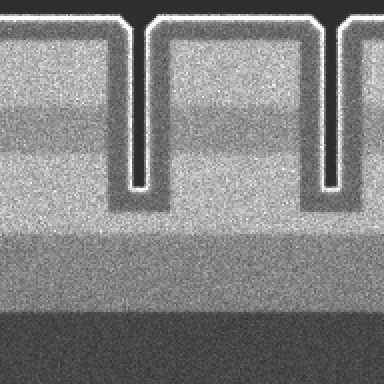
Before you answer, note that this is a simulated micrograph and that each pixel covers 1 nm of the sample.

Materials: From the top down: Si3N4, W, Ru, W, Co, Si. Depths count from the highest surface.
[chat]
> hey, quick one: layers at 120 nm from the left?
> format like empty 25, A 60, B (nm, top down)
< empty 2, Si3N4 194, W 22, Co 78, Si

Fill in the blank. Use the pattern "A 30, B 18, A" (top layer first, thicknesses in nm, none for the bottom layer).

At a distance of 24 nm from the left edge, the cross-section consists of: Si3N4 24, W 66, Ru 48, W 80, Co 78, Si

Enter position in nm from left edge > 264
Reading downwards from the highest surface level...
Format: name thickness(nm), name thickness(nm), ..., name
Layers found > Si3N4 24, W 66, Ru 48, W 80, Co 78, Si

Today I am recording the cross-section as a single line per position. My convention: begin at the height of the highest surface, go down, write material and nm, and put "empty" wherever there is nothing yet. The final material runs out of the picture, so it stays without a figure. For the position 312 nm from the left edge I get empty 2, Si3N4 194, W 22, Co 78, Si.